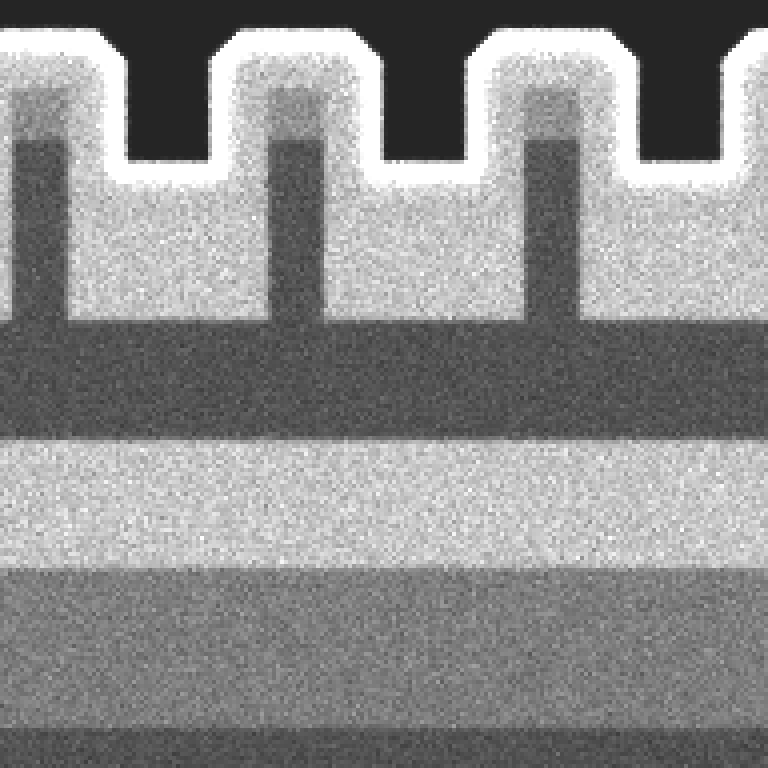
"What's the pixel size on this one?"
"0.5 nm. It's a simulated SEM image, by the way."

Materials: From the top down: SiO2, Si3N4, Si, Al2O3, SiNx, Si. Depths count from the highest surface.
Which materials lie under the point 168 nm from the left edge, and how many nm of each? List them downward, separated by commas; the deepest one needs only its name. SiO2 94, Al2O3 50, Si 60, Al2O3 64, SiNx 80, Si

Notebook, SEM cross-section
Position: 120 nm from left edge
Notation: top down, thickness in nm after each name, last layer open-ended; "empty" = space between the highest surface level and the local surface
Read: SiO2 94, Al2O3 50, Si 60, Al2O3 64, SiNx 80, Si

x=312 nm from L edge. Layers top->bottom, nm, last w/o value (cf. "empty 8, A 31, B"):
empty 10, SiO2 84, Al2O3 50, Si 60, Al2O3 64, SiNx 80, Si